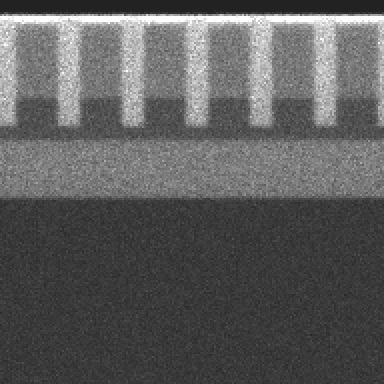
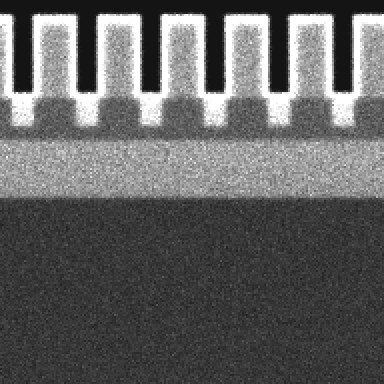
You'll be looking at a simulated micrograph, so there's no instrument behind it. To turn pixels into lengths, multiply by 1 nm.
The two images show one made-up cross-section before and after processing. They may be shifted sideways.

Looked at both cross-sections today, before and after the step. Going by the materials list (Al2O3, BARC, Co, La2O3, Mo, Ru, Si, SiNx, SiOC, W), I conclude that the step removed W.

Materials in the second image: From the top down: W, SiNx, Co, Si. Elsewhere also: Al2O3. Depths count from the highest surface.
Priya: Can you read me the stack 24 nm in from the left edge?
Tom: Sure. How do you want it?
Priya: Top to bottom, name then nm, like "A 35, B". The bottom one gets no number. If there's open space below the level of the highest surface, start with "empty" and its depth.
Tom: empty 78, W 32, SiNx 14, Co 58, Si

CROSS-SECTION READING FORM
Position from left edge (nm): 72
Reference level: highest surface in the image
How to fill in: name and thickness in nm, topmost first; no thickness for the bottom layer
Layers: Al2O3 82, SiNx 42, Co 58, Si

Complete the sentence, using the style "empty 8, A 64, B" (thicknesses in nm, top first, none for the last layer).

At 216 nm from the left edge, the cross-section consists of empty 78, W 32, SiNx 14, Co 58, Si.